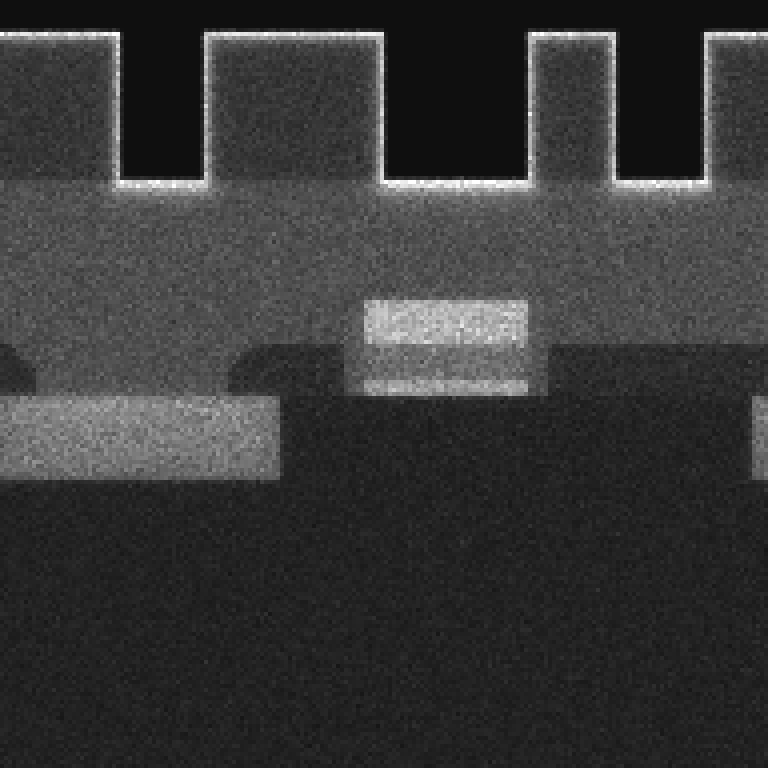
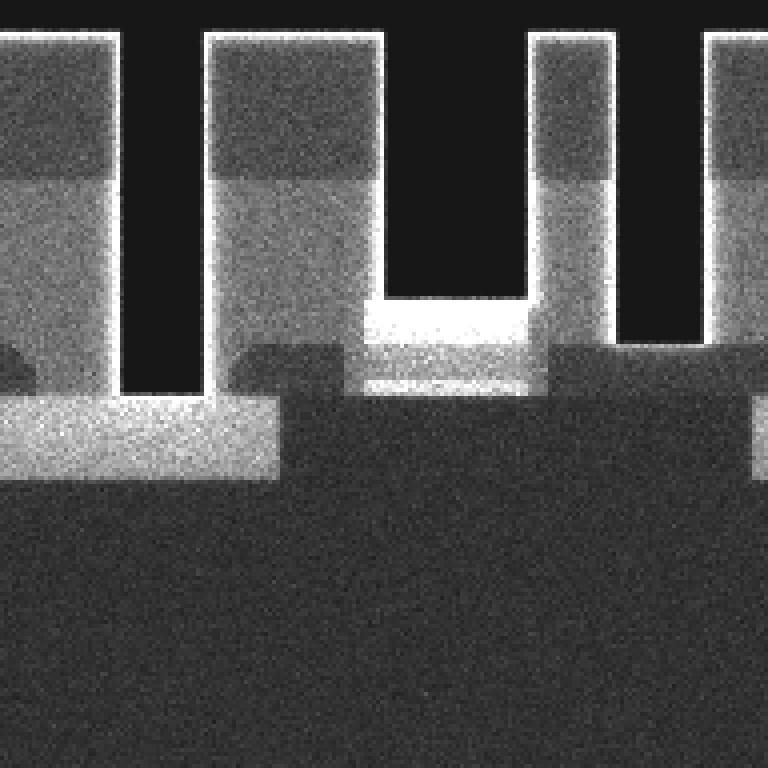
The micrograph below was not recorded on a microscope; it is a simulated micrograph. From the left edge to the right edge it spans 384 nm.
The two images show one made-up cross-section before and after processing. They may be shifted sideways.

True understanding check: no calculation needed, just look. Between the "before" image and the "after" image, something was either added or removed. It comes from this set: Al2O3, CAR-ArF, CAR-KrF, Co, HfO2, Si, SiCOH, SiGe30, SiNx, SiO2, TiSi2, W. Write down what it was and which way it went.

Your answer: SiO2 (removed)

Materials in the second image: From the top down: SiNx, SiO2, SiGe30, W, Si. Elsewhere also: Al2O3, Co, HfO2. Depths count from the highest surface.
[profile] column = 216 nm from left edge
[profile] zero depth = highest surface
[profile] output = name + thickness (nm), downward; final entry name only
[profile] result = empty 134, HfO2 22, Co 18, HfO2 8, Si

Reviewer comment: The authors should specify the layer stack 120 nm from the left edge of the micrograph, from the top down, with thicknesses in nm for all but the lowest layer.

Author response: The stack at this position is SiNx 74, SiO2 88, SiGe30 20, W 42, Si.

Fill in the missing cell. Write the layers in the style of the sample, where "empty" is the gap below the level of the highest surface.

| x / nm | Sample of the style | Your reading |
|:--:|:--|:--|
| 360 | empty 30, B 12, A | SiNx 74, SiO2 82, SiGe30 26, Si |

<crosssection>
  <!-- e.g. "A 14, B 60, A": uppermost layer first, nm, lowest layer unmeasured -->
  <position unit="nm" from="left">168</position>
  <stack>SiNx 74, SiO2 82, SiGe30 26, Si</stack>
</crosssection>